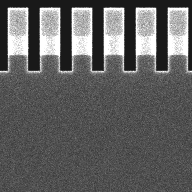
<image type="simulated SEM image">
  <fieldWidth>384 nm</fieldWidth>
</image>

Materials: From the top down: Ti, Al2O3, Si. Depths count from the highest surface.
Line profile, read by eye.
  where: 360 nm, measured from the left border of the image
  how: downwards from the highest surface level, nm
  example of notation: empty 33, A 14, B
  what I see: Ti 56, Al2O3 38, Si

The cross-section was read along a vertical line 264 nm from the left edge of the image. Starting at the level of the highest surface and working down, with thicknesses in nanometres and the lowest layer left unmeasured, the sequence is empty 126, Si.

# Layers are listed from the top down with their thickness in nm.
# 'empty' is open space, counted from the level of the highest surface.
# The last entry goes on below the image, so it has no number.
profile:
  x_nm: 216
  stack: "Ti 56, Al2O3 38, Si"